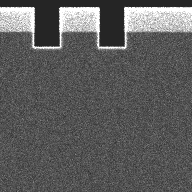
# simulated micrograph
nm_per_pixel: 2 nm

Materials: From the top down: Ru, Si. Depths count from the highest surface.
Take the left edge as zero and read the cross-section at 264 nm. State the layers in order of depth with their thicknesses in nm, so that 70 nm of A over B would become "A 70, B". Ru 48, Si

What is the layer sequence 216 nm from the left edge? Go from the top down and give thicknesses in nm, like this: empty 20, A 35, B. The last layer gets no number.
empty 78, Si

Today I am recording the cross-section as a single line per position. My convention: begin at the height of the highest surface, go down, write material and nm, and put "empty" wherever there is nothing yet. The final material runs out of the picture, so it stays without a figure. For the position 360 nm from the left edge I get Ru 48, Si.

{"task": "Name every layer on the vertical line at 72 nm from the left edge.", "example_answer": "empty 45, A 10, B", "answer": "empty 78, Si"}